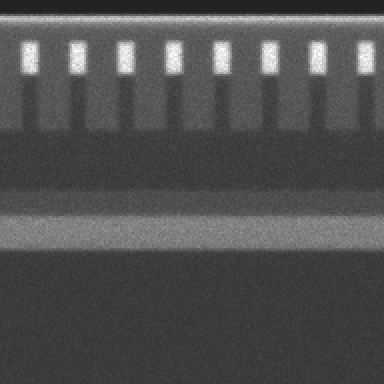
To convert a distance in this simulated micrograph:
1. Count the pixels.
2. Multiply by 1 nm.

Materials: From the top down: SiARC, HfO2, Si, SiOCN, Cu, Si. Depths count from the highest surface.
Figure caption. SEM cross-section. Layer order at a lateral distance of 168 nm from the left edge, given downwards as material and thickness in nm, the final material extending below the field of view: SiARC 26, HfO2 32, Si 116, SiOCN 26, Cu 34, Si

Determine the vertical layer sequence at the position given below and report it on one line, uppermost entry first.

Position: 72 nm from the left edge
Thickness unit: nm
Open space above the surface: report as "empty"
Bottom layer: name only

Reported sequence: SiARC 26, HfO2 32, Si 116, SiOCN 26, Cu 34, Si